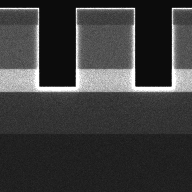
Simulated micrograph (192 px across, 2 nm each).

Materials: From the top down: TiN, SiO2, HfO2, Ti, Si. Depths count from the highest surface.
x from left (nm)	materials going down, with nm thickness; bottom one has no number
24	TiN 34, SiO2 88, HfO2 46, Ti 84, Si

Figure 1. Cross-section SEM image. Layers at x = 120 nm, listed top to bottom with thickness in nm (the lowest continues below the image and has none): empty 158, HfO2 10, Ti 84, Si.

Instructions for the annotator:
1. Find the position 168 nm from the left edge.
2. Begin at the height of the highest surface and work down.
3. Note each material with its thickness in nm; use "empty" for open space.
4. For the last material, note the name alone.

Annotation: TiN 34, SiO2 88, HfO2 46, Ti 84, Si